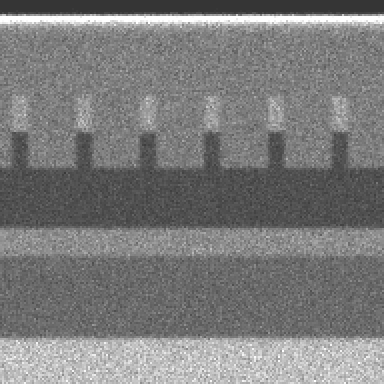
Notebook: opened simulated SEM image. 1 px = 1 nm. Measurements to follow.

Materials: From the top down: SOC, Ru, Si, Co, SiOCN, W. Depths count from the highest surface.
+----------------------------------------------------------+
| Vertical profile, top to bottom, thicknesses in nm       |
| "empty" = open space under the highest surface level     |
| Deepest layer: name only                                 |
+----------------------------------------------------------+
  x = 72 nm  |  SOC 152, Si 60, Co 28, SiOCN 82, W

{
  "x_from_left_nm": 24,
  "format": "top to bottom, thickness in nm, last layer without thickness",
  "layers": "SOC 80, Ru 36, Si 96, Co 28, SiOCN 82, W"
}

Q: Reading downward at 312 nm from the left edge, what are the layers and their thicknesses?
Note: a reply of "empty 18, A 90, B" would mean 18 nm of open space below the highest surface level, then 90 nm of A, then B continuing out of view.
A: SOC 152, Si 60, Co 28, SiOCN 82, W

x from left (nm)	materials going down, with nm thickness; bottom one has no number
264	SOC 152, Si 60, Co 28, SiOCN 82, W